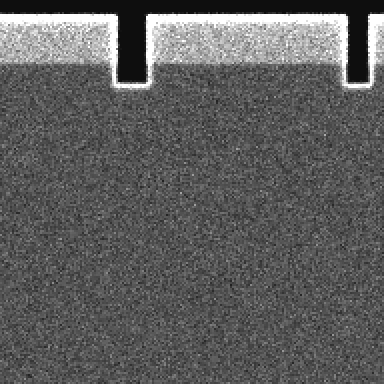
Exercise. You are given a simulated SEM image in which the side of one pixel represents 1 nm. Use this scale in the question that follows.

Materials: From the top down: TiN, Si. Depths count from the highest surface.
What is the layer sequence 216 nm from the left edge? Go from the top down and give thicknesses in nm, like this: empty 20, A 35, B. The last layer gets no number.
TiN 48, Si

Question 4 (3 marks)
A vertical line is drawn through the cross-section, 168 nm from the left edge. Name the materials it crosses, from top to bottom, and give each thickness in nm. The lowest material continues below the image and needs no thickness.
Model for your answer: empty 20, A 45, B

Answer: TiN 48, Si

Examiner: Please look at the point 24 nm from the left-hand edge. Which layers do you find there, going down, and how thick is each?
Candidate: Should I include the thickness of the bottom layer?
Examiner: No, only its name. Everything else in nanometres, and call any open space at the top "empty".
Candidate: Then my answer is TiN 48, Si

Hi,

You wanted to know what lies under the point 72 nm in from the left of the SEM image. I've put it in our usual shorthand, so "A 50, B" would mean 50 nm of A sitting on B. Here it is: TiN 48, Si